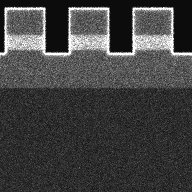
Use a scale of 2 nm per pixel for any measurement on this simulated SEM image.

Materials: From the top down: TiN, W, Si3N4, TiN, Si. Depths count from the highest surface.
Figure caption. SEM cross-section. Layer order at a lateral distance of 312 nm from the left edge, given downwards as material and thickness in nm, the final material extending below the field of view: TiN 54, W 30, Si3N4 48, TiN 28, Si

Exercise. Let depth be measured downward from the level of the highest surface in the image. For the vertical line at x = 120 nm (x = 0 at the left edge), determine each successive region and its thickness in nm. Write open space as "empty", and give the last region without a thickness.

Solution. empty 90, Si3N4 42, TiN 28, Si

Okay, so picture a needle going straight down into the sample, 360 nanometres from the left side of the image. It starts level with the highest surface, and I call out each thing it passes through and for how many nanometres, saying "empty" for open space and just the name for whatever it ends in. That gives empty 90, Si3N4 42, TiN 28, Si